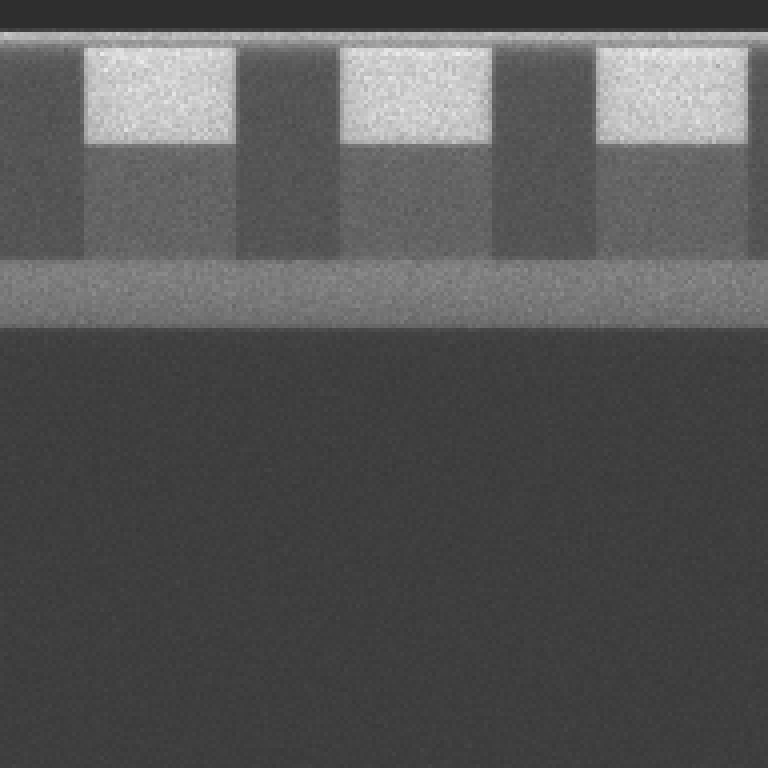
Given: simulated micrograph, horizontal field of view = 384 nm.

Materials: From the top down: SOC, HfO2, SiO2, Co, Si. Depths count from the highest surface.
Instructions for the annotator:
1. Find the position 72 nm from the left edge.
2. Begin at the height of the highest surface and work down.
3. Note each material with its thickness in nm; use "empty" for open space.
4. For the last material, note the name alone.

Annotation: SOC 8, HfO2 48, SiO2 58, Co 34, Si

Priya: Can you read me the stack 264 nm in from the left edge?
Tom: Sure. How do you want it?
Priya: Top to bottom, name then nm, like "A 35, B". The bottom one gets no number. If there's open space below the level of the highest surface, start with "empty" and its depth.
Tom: SOC 114, Co 34, Si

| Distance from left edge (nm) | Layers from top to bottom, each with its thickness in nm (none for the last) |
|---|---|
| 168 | SOC 114, Co 34, Si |